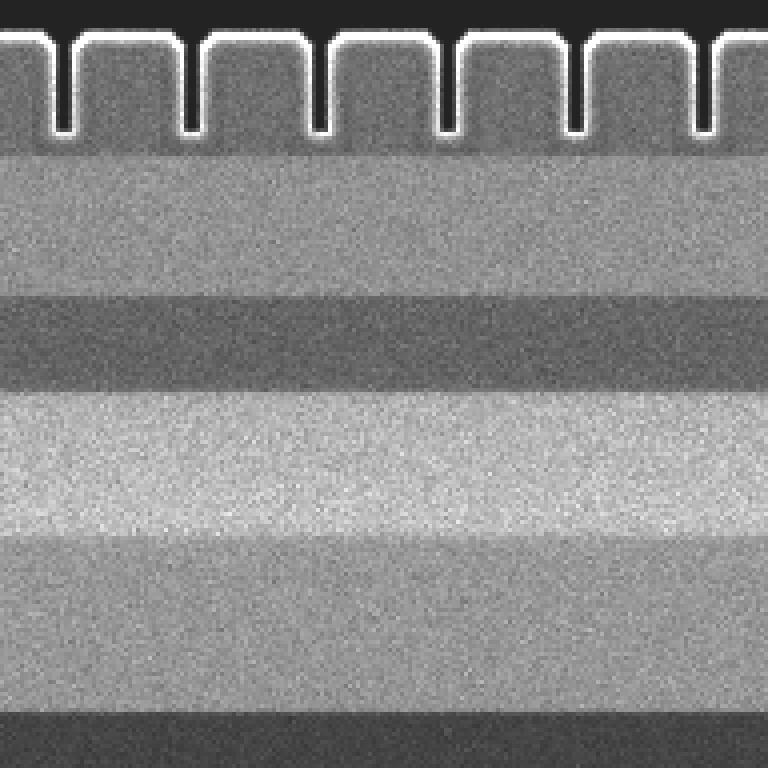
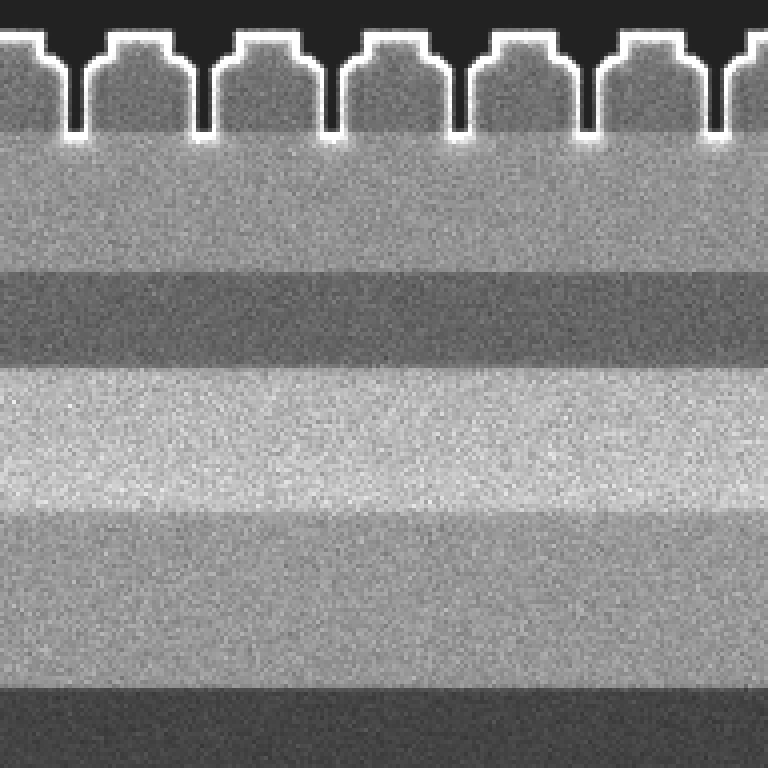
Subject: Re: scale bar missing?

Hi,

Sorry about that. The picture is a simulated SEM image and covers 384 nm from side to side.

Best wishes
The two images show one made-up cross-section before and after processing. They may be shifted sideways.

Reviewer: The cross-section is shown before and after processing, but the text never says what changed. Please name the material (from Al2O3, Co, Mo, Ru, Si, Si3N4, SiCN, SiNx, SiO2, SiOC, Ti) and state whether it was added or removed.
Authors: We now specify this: SiNx, removed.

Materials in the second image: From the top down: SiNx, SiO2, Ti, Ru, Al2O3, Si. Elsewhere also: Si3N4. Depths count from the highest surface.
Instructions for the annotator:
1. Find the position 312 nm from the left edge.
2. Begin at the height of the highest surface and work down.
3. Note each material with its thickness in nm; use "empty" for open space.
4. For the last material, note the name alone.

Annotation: Si3N4 50, SiO2 70, Ti 48, Ru 72, Al2O3 88, Si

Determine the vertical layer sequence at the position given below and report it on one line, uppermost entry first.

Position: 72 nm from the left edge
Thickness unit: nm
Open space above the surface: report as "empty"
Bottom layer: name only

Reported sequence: Si3N4 50, SiO2 70, Ti 48, Ru 72, Al2O3 88, Si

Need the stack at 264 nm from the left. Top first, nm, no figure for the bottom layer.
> Si3N4 50, SiO2 70, Ti 48, Ru 72, Al2O3 88, Si